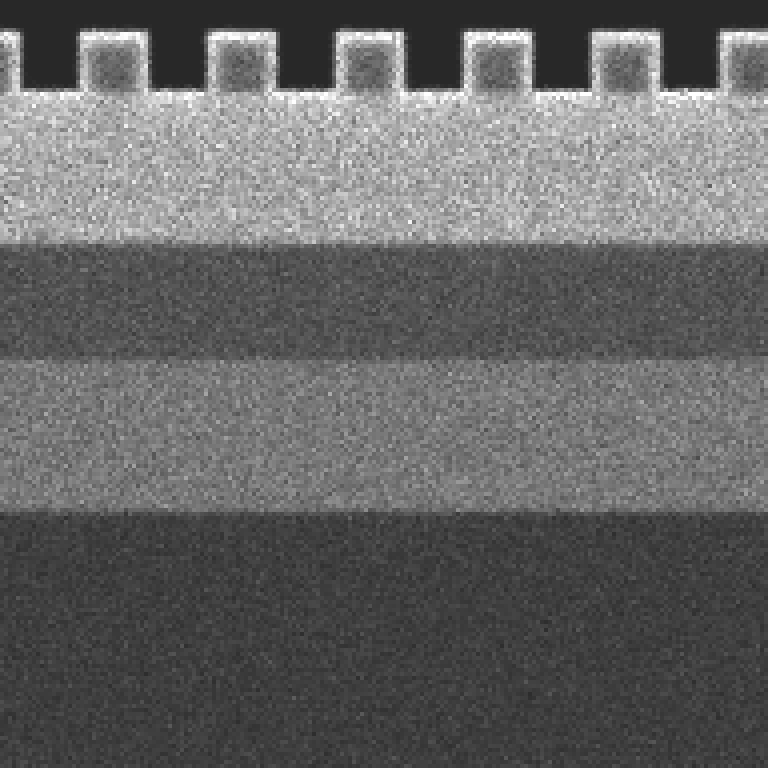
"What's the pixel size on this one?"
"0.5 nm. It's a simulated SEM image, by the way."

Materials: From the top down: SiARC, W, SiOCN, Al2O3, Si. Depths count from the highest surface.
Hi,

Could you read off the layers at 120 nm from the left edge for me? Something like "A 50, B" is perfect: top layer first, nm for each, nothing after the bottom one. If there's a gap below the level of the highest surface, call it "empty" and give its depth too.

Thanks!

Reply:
SiARC 30, W 76, SiOCN 58, Al2O3 76, Si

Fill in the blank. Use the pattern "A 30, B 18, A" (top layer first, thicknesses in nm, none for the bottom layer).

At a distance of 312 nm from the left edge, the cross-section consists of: SiARC 30, W 76, SiOCN 58, Al2O3 76, Si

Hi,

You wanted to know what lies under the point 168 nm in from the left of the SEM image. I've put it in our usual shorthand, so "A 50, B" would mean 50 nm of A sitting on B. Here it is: SiARC 30, W 76, SiOCN 58, Al2O3 76, Si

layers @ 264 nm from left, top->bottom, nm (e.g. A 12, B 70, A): SiARC 30, W 76, SiOCN 58, Al2O3 76, Si